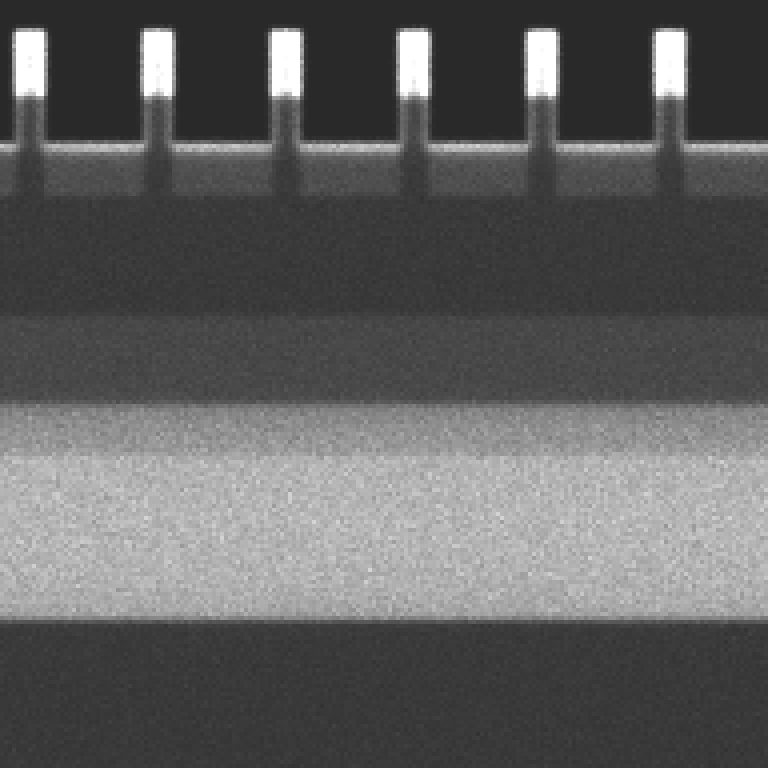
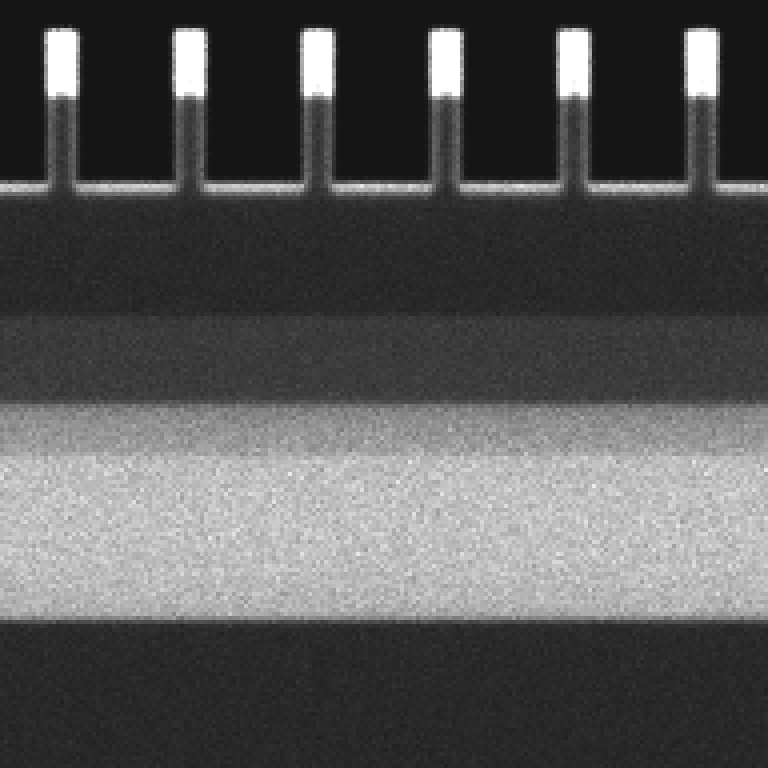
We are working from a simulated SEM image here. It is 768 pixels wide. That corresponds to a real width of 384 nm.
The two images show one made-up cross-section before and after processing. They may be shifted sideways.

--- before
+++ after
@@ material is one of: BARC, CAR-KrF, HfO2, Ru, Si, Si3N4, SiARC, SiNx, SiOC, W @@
Si3N4 removed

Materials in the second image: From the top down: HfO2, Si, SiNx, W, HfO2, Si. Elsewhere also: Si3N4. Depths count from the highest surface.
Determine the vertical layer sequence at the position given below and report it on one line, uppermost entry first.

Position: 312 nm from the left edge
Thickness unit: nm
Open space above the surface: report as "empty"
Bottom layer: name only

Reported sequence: empty 76, Si3N4 6, Si 60, SiNx 44, W 26, HfO2 82, Si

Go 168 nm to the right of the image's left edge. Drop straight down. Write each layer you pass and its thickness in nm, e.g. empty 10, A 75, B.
empty 76, Si3N4 6, Si 60, SiNx 44, W 26, HfO2 82, Si